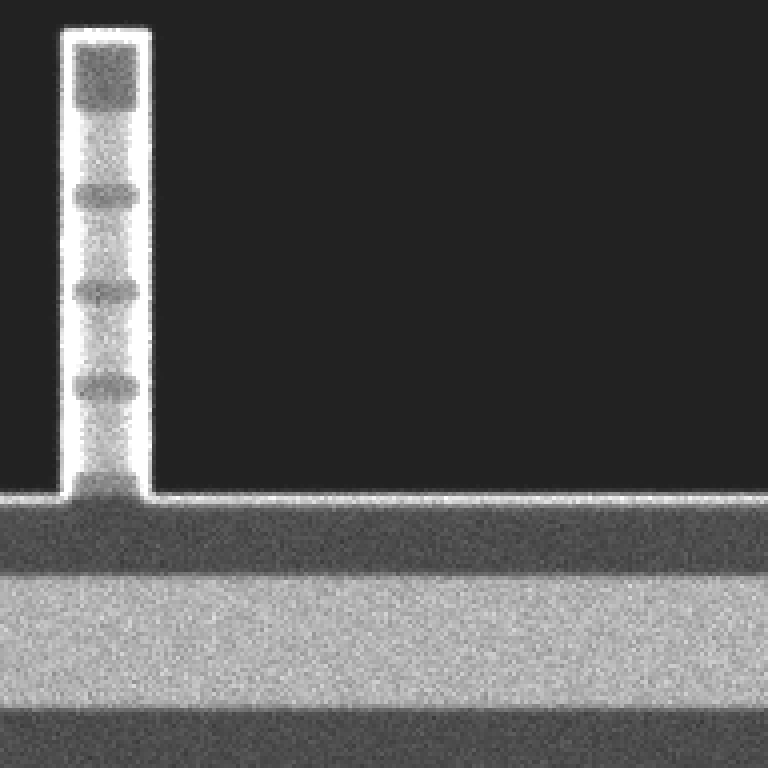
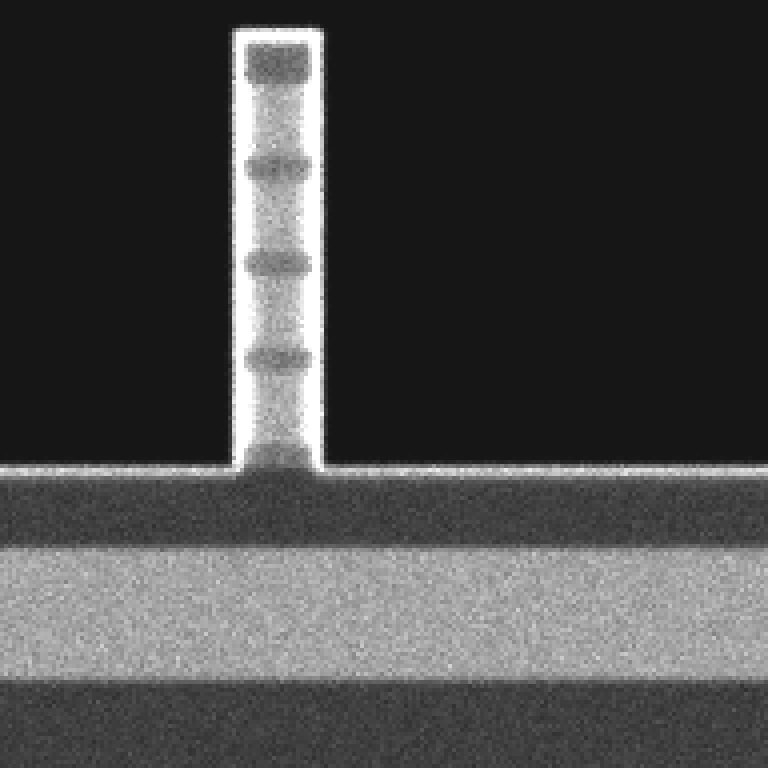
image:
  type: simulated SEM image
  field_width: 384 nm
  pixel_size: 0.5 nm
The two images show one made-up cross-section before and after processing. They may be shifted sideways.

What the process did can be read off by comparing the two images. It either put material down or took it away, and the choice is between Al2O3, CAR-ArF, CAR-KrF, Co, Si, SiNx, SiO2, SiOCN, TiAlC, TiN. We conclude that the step removed SiNx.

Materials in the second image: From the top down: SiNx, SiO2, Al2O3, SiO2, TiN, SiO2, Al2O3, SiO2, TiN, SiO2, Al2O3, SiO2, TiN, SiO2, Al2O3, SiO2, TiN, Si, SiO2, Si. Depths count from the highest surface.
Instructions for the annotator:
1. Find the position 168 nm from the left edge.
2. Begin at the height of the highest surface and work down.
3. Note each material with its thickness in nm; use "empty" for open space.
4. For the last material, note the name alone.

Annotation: empty 218, Si 40, SiO2 66, Si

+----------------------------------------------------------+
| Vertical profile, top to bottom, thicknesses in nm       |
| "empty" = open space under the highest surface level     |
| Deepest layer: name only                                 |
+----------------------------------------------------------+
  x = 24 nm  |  empty 218, Si 40, SiO2 66, Si